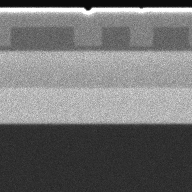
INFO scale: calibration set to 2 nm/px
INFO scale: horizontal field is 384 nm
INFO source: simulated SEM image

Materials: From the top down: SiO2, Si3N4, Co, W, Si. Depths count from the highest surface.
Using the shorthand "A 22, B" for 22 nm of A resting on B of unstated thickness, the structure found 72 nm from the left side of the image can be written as SiO2 38, Si3N4 48, Co 74, W 72, Si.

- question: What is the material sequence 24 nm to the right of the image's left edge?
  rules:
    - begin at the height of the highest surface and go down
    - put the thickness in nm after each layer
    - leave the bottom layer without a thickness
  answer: SiO2 38, Si3N4 48, Co 74, W 72, Si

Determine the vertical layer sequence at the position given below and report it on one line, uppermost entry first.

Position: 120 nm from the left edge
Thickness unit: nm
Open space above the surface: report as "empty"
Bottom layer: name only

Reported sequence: SiO2 38, Si3N4 48, Co 74, W 72, Si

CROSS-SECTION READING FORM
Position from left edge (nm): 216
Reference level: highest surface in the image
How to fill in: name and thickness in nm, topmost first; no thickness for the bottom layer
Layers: SiO2 38, Si3N4 48, Co 74, W 72, Si